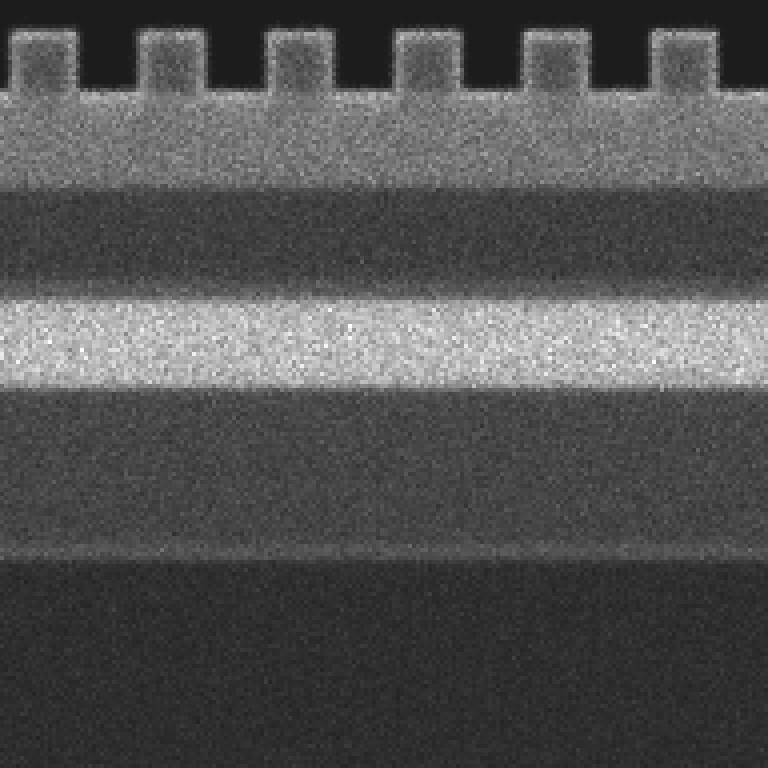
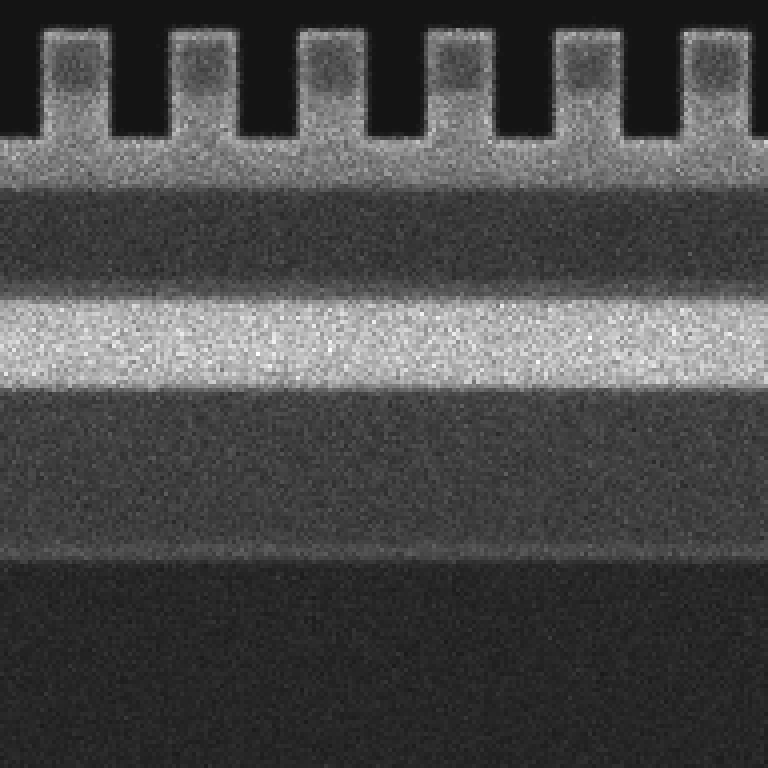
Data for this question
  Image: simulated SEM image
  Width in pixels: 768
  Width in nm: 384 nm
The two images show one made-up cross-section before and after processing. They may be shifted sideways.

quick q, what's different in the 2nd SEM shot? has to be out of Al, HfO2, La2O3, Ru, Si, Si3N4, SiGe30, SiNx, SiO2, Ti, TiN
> Ru removed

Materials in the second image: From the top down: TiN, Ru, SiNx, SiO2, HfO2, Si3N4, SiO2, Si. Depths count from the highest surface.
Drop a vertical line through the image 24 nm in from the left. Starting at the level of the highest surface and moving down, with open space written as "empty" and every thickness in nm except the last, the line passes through TiN 30, Ru 48, SiNx 46, SiO2 10, HfO2 44, Si3N4 78, SiO2 8, Si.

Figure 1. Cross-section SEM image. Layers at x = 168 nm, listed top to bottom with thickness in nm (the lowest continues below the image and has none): TiN 30, Ru 48, SiNx 46, SiO2 10, HfO2 44, Si3N4 78, SiO2 8, Si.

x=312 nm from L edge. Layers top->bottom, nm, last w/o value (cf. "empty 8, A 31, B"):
empty 54, Ru 24, SiNx 46, SiO2 10, HfO2 44, Si3N4 78, SiO2 8, Si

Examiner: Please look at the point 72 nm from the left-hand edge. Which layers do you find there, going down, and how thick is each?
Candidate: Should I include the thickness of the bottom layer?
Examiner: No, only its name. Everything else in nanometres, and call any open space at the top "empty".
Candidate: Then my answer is empty 54, Ru 24, SiNx 46, SiO2 10, HfO2 44, Si3N4 78, SiO2 8, Si